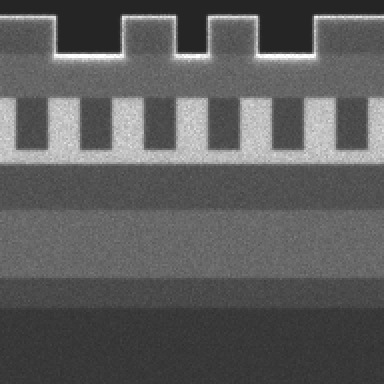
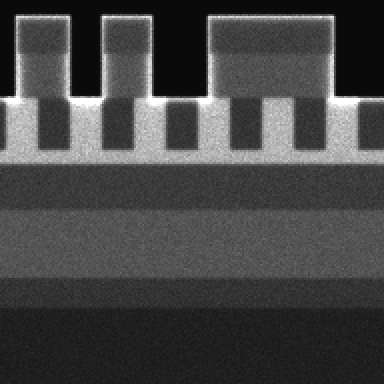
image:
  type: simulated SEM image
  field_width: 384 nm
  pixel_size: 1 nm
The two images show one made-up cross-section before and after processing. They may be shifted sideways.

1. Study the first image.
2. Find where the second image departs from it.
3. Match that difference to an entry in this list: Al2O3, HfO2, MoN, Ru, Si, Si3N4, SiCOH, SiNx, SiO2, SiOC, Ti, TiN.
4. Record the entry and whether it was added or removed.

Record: SiO2 / removed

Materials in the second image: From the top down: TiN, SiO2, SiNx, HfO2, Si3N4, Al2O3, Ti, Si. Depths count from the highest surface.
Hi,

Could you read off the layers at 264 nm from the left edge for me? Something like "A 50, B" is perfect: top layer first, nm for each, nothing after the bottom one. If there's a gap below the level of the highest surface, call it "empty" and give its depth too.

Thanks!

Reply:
TiN 38, SiO2 44, HfO2 66, Si3N4 46, Al2O3 68, Ti 30, Si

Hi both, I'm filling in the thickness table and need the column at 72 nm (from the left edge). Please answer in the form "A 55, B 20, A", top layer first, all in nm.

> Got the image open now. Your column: empty 82, HfO2 66, Si3N4 46, Al2O3 68, Ti 30, Si